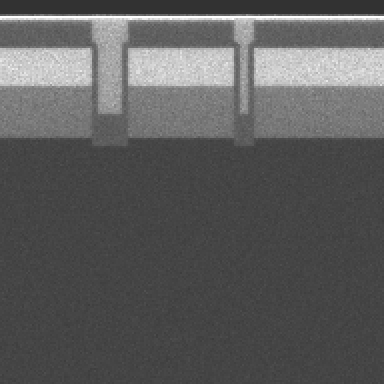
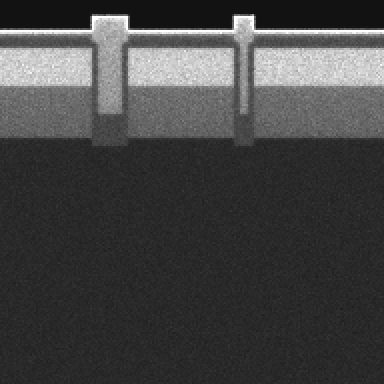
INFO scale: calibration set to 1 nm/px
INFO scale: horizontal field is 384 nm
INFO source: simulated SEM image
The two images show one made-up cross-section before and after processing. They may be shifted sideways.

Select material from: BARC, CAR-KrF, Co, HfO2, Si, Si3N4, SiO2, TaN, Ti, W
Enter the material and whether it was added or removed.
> Si3N4 / removed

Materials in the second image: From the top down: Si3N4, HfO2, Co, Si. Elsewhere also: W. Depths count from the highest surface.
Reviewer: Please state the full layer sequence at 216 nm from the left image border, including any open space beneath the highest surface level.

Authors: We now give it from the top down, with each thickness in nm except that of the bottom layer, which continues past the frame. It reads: empty 14, Si3N4 18, HfO2 38, Co 52, Si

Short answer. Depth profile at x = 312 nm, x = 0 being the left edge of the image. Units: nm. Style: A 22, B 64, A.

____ empty 14, Si3N4 18, HfO2 38, Co 52, Si